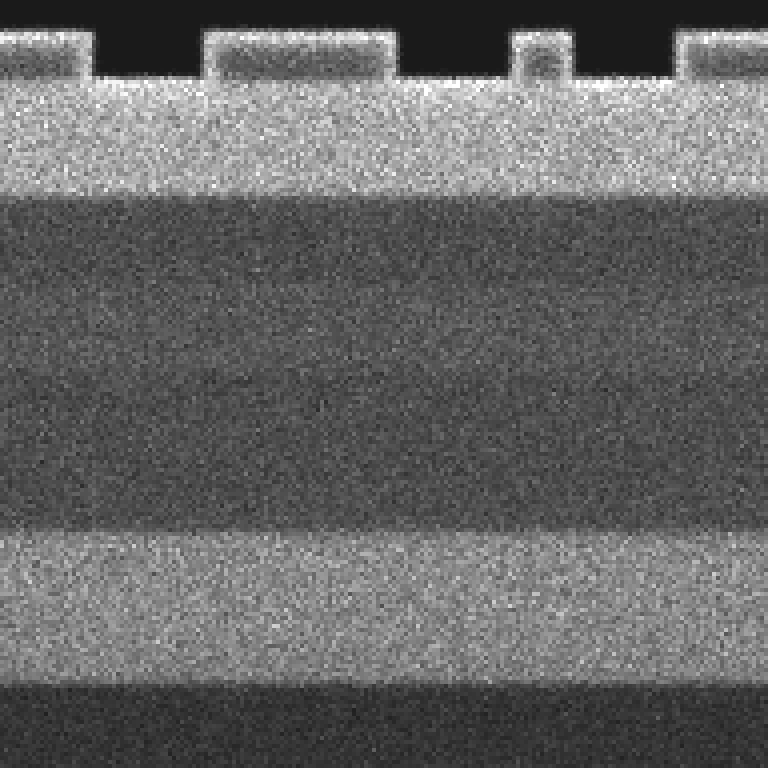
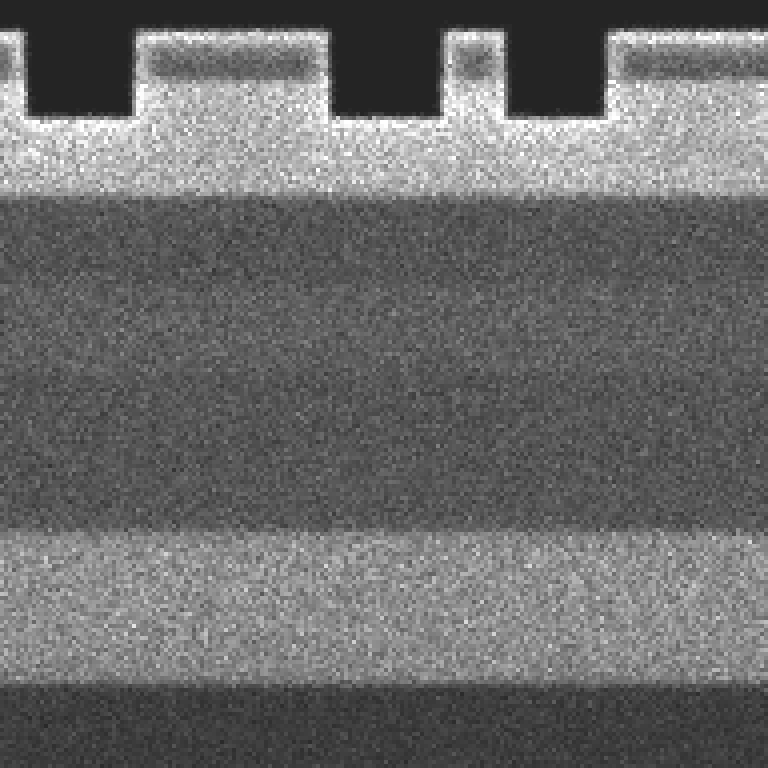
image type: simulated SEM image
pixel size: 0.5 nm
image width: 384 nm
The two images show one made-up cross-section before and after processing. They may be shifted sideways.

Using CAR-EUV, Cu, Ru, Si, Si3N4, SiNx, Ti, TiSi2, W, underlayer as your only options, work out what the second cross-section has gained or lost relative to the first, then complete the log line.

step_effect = removed W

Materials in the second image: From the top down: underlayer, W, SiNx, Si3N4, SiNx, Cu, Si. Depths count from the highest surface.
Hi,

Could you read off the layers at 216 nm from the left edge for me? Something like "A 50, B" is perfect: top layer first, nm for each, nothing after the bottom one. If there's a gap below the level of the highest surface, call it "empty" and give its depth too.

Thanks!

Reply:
empty 44, W 38, SiNx 44, Si3N4 44, SiNx 80, Cu 76, Si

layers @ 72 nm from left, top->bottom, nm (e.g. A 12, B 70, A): underlayer 24, W 58, SiNx 44, Si3N4 44, SiNx 80, Cu 76, Si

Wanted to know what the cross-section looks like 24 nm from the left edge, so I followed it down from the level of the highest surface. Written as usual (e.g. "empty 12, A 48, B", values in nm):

empty 44, W 38, SiNx 44, Si3N4 44, SiNx 80, Cu 76, Si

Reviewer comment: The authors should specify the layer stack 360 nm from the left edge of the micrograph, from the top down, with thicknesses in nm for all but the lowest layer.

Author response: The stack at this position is underlayer 24, W 58, SiNx 44, Si3N4 44, SiNx 80, Cu 76, Si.